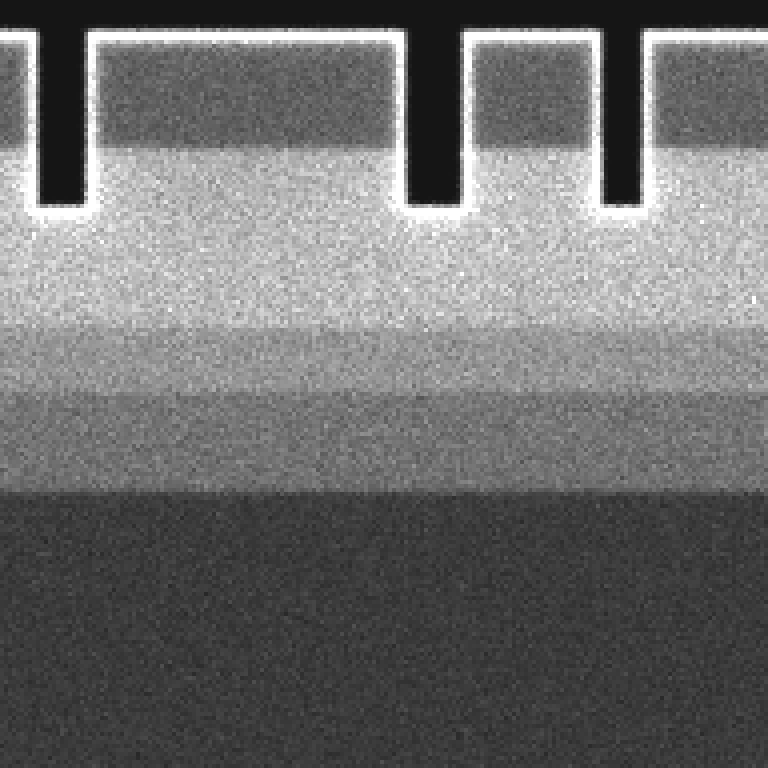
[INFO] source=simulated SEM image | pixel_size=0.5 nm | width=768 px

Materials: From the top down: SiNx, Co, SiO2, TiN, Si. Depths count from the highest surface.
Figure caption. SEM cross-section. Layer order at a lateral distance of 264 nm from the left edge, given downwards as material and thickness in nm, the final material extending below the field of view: SiNx 58, Co 90, SiO2 32, TiN 50, Si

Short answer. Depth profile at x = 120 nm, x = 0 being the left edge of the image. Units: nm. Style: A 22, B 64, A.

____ SiNx 58, Co 90, SiO2 32, TiN 50, Si